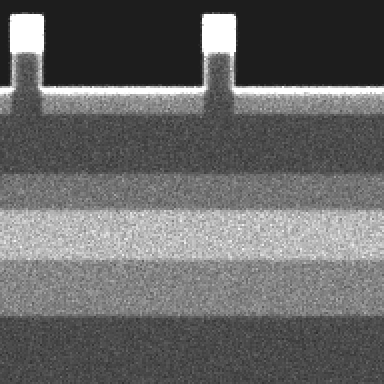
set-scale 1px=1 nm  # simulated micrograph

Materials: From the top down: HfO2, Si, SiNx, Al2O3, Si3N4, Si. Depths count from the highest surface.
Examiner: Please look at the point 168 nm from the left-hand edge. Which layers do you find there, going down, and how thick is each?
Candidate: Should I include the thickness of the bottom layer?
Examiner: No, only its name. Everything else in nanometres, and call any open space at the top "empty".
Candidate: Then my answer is empty 72, Si3N4 26, Si 60, SiNx 36, Al2O3 50, Si3N4 56, Si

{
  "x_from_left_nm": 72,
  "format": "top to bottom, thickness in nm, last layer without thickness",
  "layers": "empty 72, Si3N4 26, Si 60, SiNx 36, Al2O3 50, Si3N4 56, Si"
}